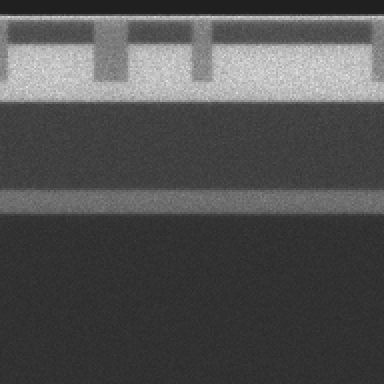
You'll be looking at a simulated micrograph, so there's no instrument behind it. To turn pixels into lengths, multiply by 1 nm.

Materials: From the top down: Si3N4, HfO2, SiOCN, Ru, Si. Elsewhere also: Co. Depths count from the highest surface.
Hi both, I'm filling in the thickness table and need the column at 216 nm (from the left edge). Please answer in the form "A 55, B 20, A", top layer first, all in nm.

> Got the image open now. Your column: Si3N4 28, HfO2 58, SiOCN 88, Ru 24, Si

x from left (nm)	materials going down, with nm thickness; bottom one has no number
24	Si3N4 28, HfO2 58, SiOCN 88, Ru 24, Si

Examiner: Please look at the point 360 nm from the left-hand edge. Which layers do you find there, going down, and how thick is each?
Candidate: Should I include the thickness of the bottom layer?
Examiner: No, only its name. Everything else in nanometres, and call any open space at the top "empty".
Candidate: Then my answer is Si3N4 28, HfO2 58, SiOCN 88, Ru 24, Si